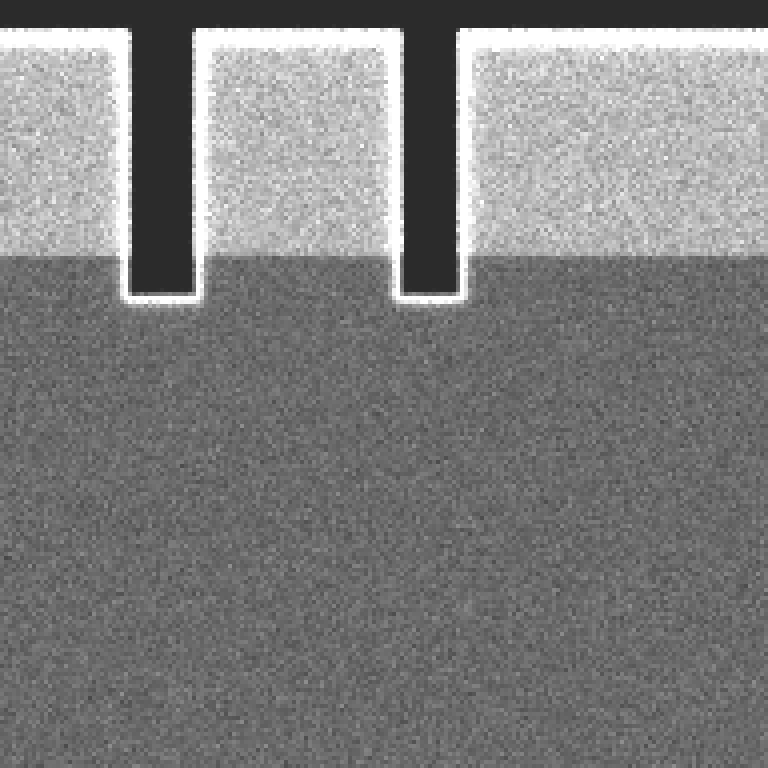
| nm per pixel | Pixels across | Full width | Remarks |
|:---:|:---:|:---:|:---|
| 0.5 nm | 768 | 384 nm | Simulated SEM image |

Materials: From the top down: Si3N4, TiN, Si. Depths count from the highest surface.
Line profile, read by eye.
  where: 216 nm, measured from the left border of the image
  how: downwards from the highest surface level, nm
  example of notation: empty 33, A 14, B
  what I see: empty 132, Si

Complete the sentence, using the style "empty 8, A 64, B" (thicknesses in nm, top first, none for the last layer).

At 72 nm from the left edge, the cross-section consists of empty 132, Si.